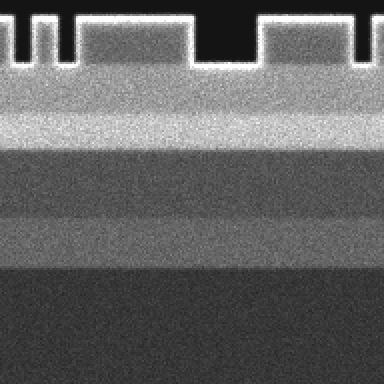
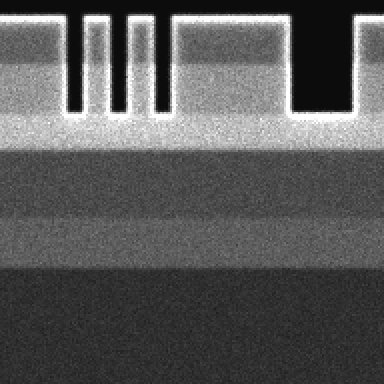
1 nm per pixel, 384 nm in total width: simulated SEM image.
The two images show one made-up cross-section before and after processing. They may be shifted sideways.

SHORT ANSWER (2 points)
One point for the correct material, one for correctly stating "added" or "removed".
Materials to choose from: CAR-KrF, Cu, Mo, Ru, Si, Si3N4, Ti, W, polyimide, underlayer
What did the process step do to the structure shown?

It removed Ru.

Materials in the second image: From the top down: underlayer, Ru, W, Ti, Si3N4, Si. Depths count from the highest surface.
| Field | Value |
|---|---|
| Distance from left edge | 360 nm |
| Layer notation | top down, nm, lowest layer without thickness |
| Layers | underlayer 48, Ru 50, W 36, Ti 68, Si3N4 50, Si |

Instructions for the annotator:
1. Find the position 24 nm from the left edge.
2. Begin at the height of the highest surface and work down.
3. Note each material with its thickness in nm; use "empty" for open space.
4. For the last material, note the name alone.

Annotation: underlayer 48, Ru 50, W 36, Ti 68, Si3N4 50, Si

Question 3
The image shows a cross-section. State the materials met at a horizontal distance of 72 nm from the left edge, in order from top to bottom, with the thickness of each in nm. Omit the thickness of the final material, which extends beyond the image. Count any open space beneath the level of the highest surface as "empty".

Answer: empty 98, W 36, Ti 68, Si3N4 50, Si